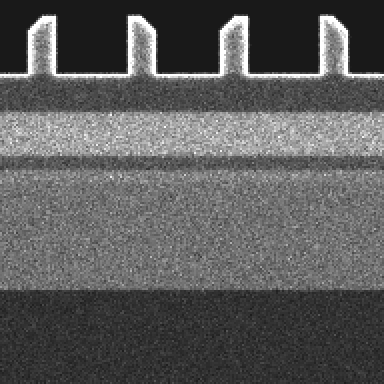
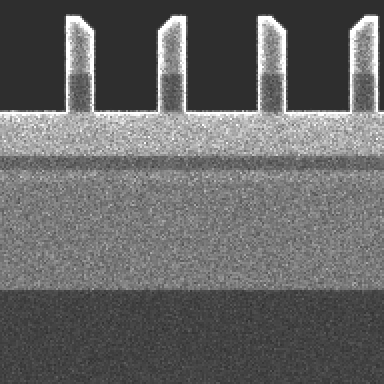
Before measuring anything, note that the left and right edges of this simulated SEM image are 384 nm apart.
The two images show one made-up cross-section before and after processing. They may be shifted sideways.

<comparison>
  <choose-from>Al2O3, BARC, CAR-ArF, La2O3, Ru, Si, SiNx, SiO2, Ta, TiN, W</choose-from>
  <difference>SiNx removed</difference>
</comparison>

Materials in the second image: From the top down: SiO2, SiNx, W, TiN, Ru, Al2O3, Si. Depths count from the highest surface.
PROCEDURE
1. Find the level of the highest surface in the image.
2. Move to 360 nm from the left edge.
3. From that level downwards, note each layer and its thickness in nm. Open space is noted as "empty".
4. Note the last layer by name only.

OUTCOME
empty 4, SiO2 54, SiNx 38, W 44, TiN 14, Ru 12, Al2O3 108, Si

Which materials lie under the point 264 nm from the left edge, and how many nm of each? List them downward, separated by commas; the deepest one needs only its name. SiO2 58, SiNx 38, W 44, TiN 14, Ru 12, Al2O3 108, Si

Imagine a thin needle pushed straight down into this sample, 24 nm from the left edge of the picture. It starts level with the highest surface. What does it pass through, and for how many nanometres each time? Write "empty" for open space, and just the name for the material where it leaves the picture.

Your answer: empty 96, W 44, TiN 14, Ru 12, Al2O3 108, Si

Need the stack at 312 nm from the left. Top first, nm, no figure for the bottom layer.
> empty 96, W 44, TiN 14, Ru 12, Al2O3 108, Si